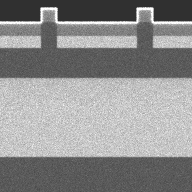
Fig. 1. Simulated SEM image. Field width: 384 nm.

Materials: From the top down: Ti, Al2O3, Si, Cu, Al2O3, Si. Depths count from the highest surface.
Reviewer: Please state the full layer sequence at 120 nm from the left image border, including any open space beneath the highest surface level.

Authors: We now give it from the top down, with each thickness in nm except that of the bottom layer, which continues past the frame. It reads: empty 28, Ti 28, Al2O3 24, Si 60, Cu 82, Al2O3 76, Si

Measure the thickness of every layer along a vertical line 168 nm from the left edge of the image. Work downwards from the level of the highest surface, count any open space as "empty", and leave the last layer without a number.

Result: empty 28, Ti 28, Al2O3 24, Si 60, Cu 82, Al2O3 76, Si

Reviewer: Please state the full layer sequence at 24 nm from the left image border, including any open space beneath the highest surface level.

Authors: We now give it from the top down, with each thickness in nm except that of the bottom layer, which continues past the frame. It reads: empty 28, Ti 28, Al2O3 24, Si 60, Cu 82, Al2O3 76, Si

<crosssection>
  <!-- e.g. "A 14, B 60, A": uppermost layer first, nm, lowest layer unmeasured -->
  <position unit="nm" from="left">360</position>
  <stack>empty 28, Ti 28, Al2O3 24, Si 60, Cu 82, Al2O3 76, Si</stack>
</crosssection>